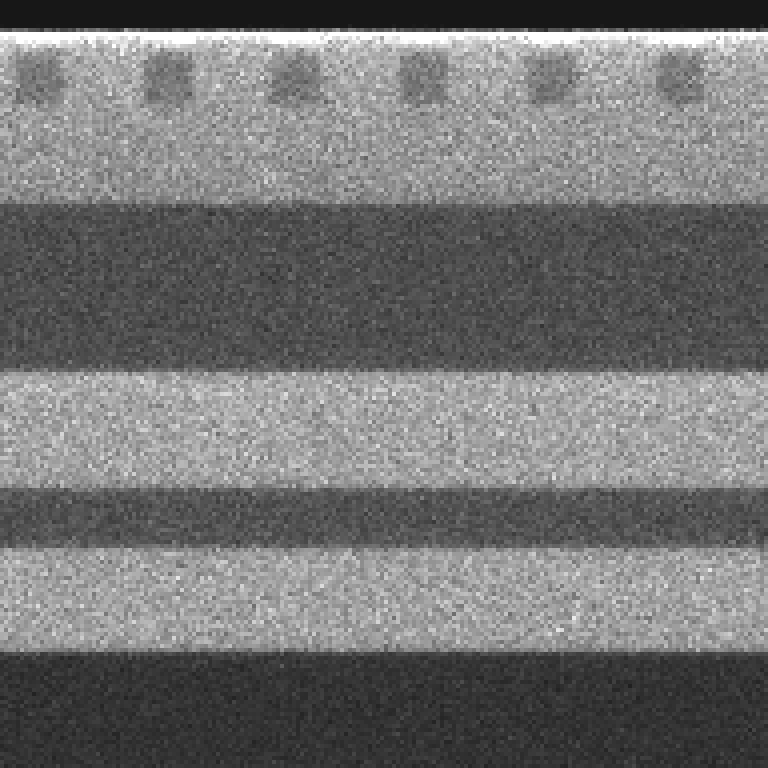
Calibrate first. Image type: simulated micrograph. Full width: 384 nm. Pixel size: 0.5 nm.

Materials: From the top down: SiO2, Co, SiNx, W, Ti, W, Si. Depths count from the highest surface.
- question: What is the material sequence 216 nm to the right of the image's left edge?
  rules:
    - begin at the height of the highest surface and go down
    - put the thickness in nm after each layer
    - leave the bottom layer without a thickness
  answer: SiO2 36, Co 50, SiNx 84, W 58, Ti 30, W 52, Si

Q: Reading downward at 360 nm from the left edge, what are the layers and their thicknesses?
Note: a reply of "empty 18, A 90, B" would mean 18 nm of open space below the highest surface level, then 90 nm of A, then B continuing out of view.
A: Co 86, SiNx 84, W 58, Ti 30, W 52, Si